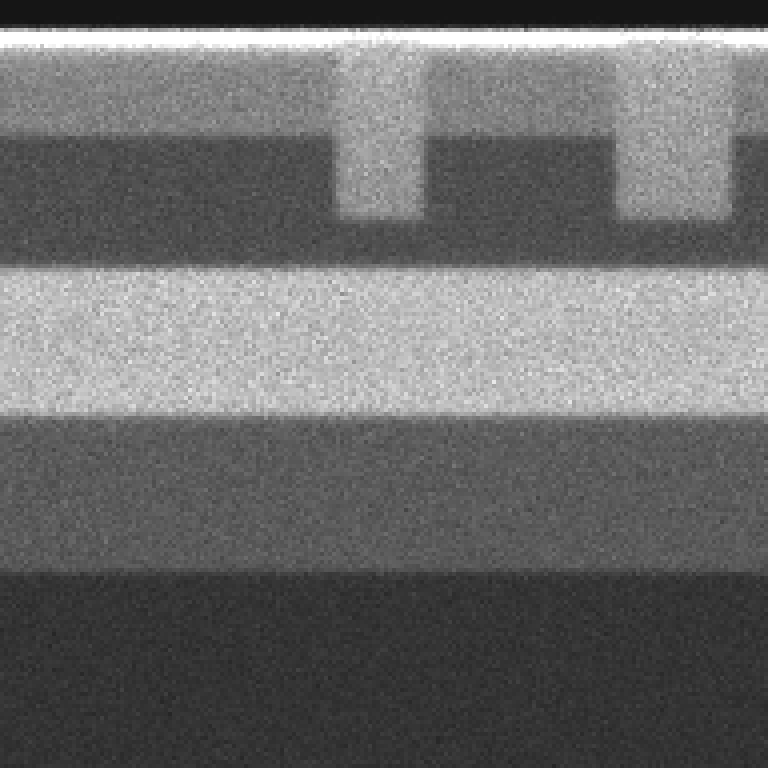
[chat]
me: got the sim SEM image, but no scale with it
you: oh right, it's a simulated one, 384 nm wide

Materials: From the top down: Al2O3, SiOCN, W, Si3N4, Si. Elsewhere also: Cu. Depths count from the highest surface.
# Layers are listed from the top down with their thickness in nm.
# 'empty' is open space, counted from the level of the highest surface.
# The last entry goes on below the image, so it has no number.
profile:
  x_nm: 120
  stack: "Al2O3 52, SiOCN 66, W 74, Si3N4 78, Si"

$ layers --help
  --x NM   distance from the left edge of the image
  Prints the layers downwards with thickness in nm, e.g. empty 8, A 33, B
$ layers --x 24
Al2O3 52, SiOCN 66, W 74, Si3N4 78, Si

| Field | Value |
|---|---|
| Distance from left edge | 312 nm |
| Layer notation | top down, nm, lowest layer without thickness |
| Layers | Cu 94, SiOCN 24, W 74, Si3N4 78, Si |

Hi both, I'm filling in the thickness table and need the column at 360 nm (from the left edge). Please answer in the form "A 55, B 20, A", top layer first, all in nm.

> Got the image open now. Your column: Cu 94, SiOCN 24, W 74, Si3N4 78, Si